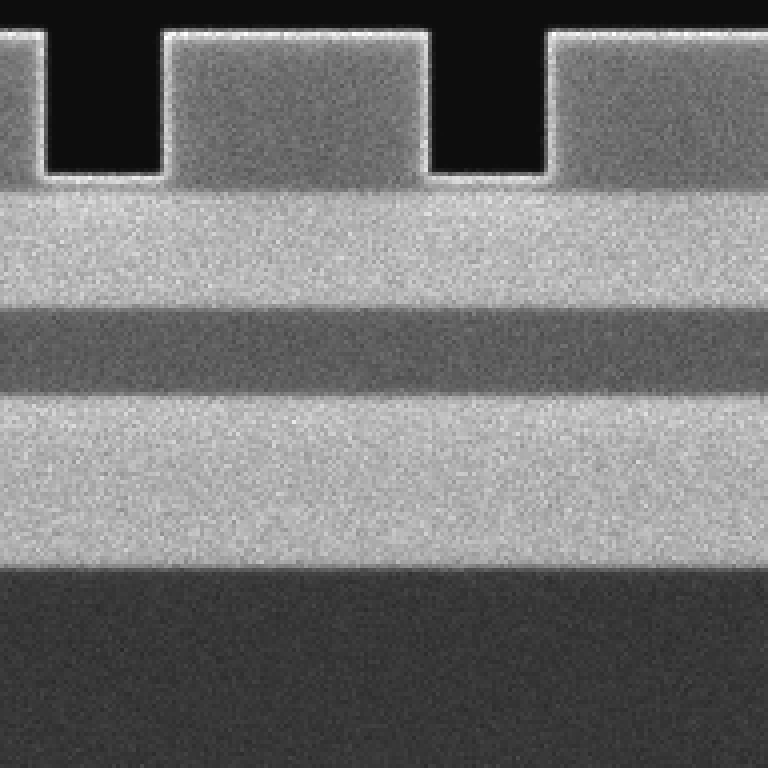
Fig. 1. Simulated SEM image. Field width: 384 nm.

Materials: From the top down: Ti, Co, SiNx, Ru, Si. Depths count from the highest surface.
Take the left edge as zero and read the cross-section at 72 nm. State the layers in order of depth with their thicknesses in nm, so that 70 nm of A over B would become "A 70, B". empty 72, Ti 8, Co 58, SiNx 44, Ru 86, Si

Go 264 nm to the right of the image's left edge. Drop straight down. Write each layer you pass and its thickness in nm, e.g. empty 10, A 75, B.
empty 72, Ti 8, Co 58, SiNx 44, Ru 86, Si